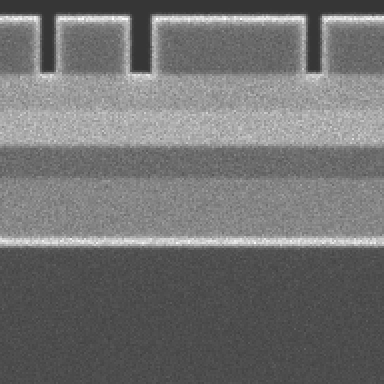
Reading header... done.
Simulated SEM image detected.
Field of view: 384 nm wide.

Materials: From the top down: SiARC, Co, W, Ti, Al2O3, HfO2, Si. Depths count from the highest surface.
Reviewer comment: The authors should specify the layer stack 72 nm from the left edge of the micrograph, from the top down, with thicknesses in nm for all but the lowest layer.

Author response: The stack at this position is SiARC 58, Co 36, W 36, Ti 32, Al2O3 60, HfO2 8, Si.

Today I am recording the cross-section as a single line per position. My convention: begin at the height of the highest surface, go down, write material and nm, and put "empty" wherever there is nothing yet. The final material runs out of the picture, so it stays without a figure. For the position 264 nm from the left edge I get SiARC 58, Co 36, W 36, Ti 32, Al2O3 60, HfO2 8, Si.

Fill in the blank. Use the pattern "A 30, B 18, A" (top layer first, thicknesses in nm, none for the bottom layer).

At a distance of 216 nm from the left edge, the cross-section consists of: SiARC 58, Co 36, W 36, Ti 32, Al2O3 60, HfO2 8, Si